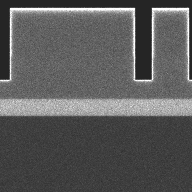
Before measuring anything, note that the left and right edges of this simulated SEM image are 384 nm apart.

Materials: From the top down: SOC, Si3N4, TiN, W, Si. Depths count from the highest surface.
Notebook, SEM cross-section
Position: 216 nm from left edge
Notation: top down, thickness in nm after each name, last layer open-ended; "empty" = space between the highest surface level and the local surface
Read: SOC 20, Si3N4 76, TiN 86, W 34, Si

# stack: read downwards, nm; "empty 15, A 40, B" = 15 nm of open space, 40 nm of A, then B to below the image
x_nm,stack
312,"SOC 20, Si3N4 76, TiN 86, W 34, Si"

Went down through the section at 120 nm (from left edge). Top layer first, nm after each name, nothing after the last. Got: SOC 20, Si3N4 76, TiN 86, W 34, Si